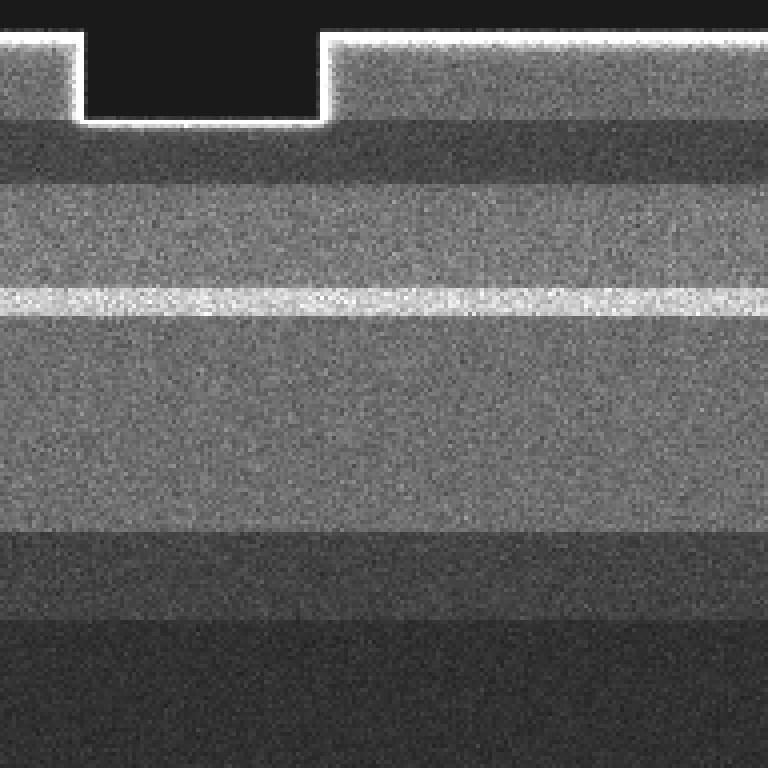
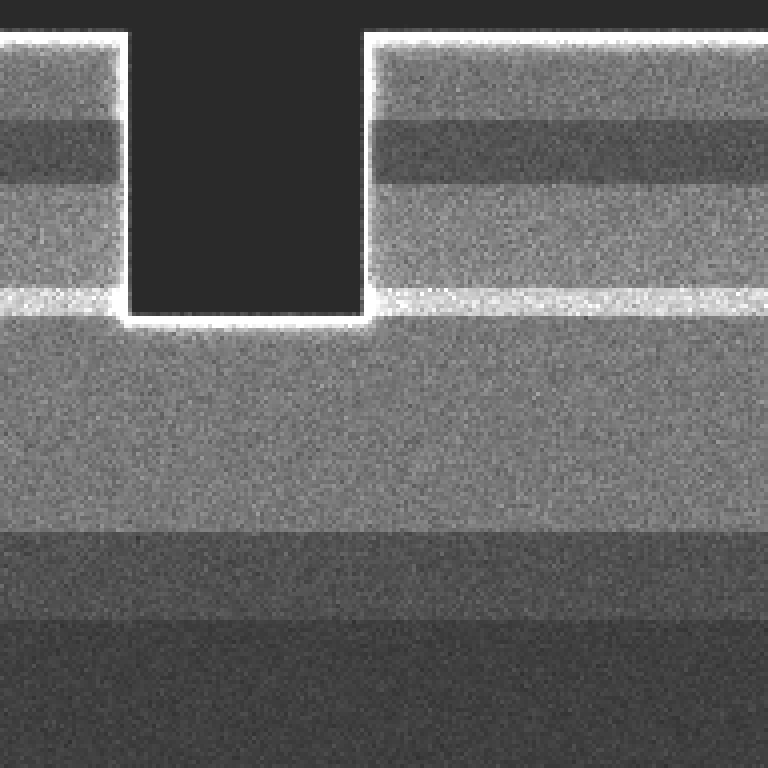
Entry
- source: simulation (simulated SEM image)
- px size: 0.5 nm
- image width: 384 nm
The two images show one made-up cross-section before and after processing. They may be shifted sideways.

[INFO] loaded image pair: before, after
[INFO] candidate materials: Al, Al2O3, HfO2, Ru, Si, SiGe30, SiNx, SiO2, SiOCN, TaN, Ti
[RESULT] removed HfO2 and Ru and SiNx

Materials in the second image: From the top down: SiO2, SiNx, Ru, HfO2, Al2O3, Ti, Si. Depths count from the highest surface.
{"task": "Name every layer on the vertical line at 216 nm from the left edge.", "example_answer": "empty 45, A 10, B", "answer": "SiO2 44, SiNx 32, Ru 52, HfO2 14, Al2O3 108, Ti 44, Si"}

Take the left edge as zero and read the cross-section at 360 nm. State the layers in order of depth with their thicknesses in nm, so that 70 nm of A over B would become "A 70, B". SiO2 44, SiNx 32, Ru 52, HfO2 14, Al2O3 108, Ti 44, Si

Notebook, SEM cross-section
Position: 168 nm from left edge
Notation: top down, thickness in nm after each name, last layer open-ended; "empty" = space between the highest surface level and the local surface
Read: empty 142, Al2O3 108, Ti 44, Si